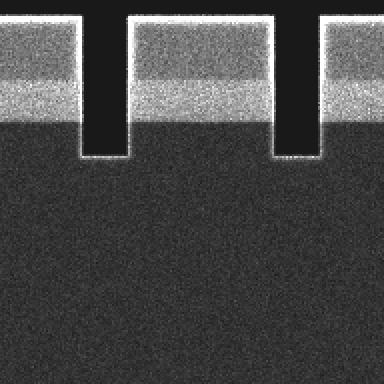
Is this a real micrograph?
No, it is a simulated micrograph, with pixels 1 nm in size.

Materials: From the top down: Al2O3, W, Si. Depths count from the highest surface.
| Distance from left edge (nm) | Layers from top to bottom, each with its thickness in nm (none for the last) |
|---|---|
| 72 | Al2O3 64, W 42, Si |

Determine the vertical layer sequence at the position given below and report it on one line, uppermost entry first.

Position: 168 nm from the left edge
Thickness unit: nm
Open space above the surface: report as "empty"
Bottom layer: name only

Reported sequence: Al2O3 64, W 42, Si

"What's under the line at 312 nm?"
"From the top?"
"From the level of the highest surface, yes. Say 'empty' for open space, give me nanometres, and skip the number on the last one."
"empty 140, Si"